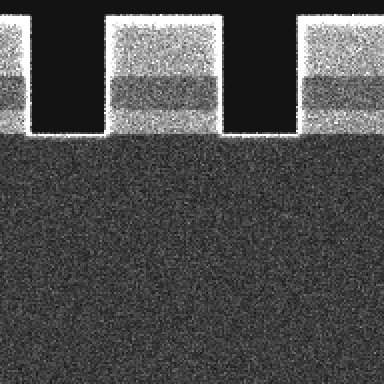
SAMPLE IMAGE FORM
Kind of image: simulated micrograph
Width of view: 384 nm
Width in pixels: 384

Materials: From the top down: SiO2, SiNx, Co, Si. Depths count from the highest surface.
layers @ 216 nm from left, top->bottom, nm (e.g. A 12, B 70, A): SiO2 60, SiNx 34, Co 24, Si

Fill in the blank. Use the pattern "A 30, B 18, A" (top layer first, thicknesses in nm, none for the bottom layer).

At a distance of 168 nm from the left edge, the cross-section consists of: SiO2 60, SiNx 34, Co 24, Si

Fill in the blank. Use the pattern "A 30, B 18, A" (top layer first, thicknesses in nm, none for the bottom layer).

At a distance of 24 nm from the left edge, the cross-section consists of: SiO2 60, SiNx 34, Co 24, Si